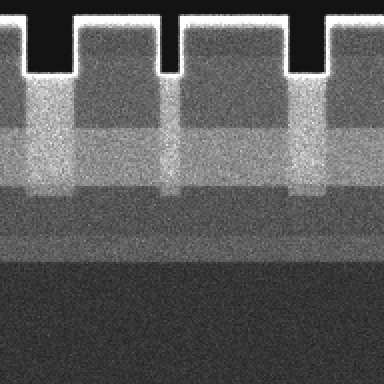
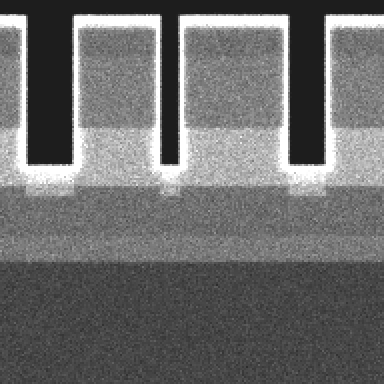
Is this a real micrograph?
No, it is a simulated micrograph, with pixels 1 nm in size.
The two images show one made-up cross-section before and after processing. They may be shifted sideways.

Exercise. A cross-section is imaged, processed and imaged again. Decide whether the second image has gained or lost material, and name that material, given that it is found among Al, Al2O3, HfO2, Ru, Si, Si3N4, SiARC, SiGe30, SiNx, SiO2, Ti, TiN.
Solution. removed: Ru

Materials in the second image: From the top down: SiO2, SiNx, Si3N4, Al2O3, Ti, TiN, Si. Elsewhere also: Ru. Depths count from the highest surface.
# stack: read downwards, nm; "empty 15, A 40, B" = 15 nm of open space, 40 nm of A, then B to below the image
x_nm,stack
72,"empty 150, Ru 18, SiO2 12, SiNx 28, Ti 12, TiN 26, Si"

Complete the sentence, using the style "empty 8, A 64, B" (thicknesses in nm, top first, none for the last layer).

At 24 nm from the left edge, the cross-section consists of SiO2 12, SiNx 28, Si3N4 72, Al2O3 58, Ti 50, TiN 26, Si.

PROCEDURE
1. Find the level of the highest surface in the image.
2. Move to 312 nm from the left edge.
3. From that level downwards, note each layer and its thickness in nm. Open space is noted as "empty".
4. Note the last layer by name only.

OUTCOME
empty 150, Ru 18, SiO2 12, SiNx 28, Ti 12, TiN 26, Si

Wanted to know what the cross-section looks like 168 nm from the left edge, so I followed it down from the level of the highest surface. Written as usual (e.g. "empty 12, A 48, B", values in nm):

empty 150, Ru 18, SiO2 12, SiNx 28, Ti 12, TiN 26, Si